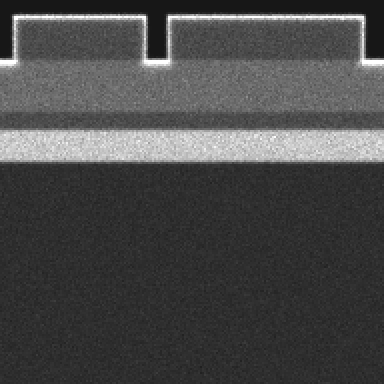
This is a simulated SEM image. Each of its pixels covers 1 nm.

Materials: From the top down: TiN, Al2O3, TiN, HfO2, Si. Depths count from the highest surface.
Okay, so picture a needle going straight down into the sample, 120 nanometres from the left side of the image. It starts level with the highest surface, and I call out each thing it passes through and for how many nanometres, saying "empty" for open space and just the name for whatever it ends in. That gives TiN 44, Al2O3 52, TiN 18, HfO2 32, Si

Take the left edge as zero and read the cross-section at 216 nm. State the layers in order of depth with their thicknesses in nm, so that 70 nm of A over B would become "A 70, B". TiN 44, Al2O3 52, TiN 18, HfO2 32, Si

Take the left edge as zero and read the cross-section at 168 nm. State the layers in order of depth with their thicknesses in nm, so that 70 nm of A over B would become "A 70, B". TiN 44, Al2O3 52, TiN 18, HfO2 32, Si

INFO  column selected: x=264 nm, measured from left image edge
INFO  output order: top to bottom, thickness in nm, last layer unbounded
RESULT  TiN 44, Al2O3 52, TiN 18, HfO2 32, Si